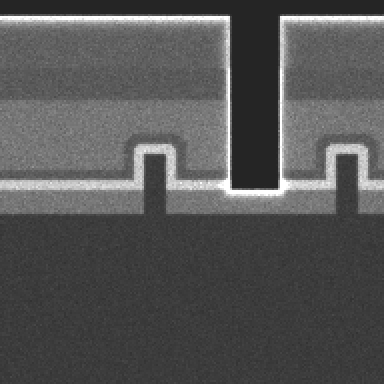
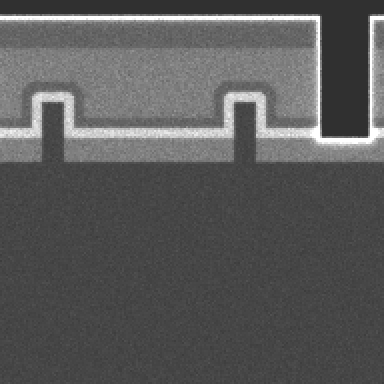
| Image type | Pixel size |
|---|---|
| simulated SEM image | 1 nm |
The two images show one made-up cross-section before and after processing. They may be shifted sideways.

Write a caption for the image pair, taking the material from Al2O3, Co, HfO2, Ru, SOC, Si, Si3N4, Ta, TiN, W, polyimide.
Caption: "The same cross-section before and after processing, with SOC removed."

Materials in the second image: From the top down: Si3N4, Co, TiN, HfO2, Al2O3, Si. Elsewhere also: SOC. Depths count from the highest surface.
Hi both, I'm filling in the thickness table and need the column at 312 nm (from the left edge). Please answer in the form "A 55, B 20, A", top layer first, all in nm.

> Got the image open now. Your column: Si3N4 32, Co 70, TiN 10, HfO2 10, Al2O3 24, Si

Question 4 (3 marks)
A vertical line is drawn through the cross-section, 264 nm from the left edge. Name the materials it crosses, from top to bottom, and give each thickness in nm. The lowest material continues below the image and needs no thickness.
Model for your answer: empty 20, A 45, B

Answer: Si3N4 32, Co 34, TiN 14, HfO2 42, Al2O3 24, Si